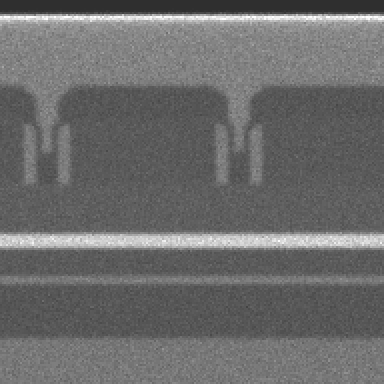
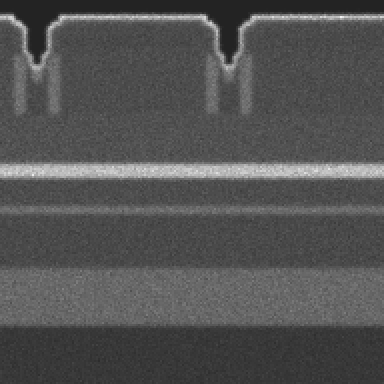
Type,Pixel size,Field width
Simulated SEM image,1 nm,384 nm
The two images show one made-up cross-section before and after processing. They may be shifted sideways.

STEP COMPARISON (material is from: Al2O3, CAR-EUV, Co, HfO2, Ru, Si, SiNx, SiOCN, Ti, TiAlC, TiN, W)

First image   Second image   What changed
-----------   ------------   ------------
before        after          Ru, removed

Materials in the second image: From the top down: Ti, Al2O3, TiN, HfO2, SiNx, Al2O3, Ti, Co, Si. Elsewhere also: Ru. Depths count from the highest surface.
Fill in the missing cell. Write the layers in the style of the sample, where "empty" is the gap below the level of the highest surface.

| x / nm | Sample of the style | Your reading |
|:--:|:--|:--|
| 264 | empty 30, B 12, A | Ti 32, SiNx 66, TiN 50, HfO2 14, SiNx 28, Al2O3 8, Ti 54, Co 58, Si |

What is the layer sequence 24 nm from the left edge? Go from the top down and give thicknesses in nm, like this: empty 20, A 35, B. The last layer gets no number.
empty 12, Ti 32, Al2O3 54, TiN 50, HfO2 14, SiNx 28, Al2O3 8, Ti 54, Co 58, Si